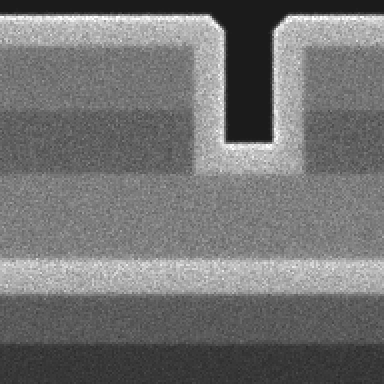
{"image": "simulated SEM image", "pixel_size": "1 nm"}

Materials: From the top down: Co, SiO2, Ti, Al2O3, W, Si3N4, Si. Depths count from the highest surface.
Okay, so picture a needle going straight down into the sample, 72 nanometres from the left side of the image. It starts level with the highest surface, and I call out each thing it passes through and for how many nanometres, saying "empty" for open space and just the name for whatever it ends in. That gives Co 30, SiO2 64, Ti 64, Al2O3 86, W 34, Si3N4 50, Si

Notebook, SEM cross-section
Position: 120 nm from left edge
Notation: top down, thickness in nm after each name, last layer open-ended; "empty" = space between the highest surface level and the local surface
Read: Co 30, SiO2 64, Ti 64, Al2O3 86, W 34, Si3N4 50, Si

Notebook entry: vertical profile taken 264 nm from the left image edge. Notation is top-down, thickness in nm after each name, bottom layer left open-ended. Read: empty 128, Co 30, Al2O3 86, W 34, Si3N4 50, Si